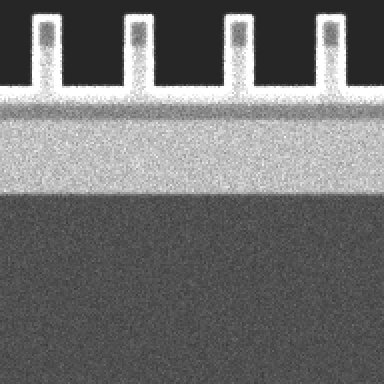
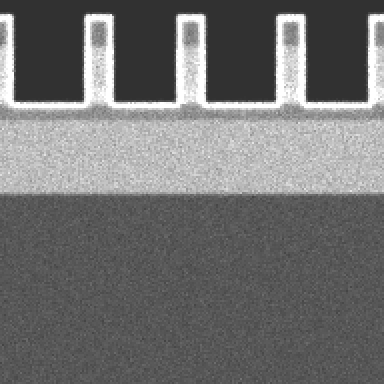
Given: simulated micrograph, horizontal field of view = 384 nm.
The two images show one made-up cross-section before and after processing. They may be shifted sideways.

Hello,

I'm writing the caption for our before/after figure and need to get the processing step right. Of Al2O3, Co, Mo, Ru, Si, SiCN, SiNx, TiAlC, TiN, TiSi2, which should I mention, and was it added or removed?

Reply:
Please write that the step removed Ru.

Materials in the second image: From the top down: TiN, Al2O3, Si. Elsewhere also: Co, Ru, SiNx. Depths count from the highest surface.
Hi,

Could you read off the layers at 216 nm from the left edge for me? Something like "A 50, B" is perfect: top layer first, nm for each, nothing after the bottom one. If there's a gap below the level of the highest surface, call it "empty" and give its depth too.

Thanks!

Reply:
empty 88, TiN 16, Al2O3 74, Si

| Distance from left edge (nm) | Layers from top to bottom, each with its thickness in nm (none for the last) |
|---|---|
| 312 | empty 88, TiN 16, Al2O3 74, Si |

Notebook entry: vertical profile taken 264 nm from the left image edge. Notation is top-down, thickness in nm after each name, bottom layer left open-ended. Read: empty 88, TiN 16, Al2O3 74, Si